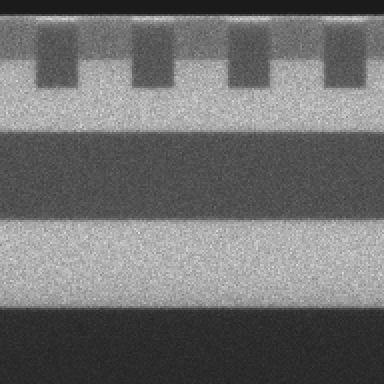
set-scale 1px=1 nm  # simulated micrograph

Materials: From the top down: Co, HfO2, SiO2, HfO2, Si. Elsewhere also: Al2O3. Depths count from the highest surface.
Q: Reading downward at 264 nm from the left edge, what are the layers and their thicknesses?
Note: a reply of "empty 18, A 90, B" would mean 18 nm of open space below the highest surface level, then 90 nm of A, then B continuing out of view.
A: Al2O3 72, HfO2 44, SiO2 88, HfO2 88, Si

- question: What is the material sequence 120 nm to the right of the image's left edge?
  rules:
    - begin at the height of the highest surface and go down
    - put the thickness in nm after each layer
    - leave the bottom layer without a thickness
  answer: Co 44, HfO2 72, SiO2 88, HfO2 88, Si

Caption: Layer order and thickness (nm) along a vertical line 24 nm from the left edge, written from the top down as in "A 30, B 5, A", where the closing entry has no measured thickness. Co 44, HfO2 72, SiO2 88, HfO2 88, Si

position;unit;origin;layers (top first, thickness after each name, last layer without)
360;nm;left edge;Al2O3 72, HfO2 44, SiO2 88, HfO2 88, Si